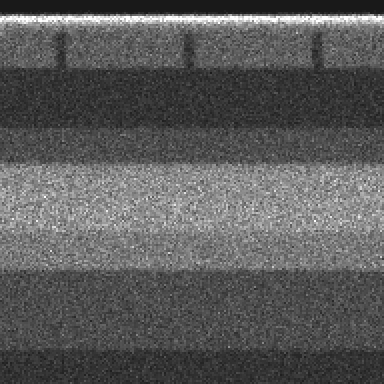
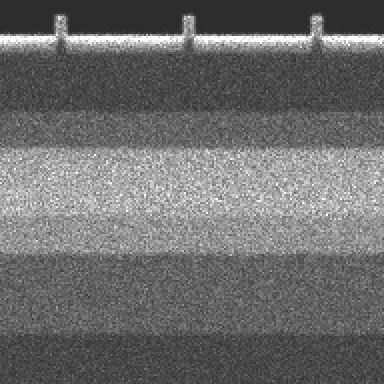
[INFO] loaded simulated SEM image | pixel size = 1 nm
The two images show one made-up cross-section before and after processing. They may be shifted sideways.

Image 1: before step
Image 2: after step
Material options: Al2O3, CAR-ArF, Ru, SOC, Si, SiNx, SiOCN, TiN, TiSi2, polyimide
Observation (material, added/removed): SOC, removed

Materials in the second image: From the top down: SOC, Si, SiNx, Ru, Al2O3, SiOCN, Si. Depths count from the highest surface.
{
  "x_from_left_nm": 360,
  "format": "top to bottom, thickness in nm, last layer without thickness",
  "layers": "empty 20, SOC 16, Si 60, SiNx 36, Ru 68, Al2O3 38, SiOCN 80, Si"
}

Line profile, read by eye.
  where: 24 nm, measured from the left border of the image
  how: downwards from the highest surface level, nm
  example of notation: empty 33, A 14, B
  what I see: empty 20, SOC 16, Si 60, SiNx 36, Ru 68, Al2O3 38, SiOCN 80, Si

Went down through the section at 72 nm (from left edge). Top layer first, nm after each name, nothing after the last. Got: empty 20, SOC 16, Si 60, SiNx 36, Ru 68, Al2O3 38, SiOCN 80, Si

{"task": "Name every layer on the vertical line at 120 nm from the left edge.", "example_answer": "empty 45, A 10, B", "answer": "empty 20, SOC 16, Si 60, SiNx 36, Ru 68, Al2O3 38, SiOCN 80, Si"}